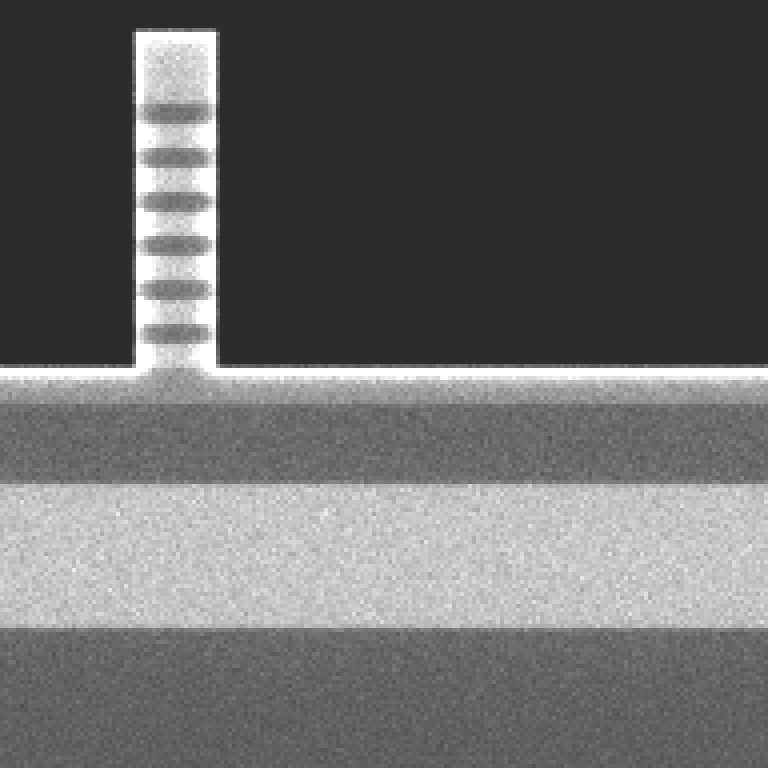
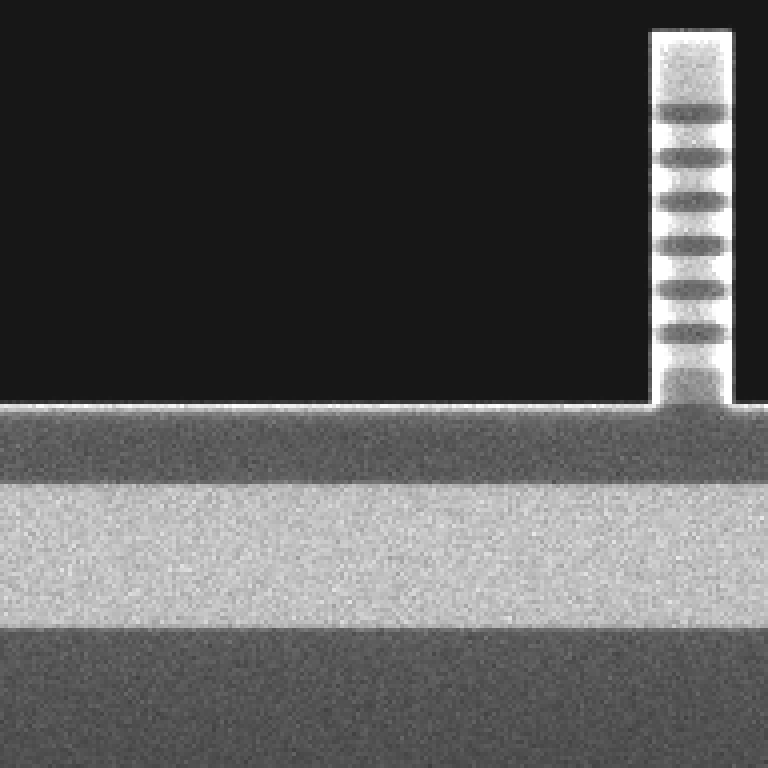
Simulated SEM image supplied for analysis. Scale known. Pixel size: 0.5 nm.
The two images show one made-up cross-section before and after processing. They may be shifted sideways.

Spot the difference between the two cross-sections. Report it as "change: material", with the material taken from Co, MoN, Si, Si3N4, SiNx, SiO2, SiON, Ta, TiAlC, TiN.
removed: SiNx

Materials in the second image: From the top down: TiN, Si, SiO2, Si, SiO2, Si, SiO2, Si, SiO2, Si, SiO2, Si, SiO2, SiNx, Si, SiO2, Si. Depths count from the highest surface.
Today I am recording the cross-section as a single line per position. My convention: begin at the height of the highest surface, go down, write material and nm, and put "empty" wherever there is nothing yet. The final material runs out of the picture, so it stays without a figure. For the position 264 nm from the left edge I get empty 186, Si 40, SiO2 72, Si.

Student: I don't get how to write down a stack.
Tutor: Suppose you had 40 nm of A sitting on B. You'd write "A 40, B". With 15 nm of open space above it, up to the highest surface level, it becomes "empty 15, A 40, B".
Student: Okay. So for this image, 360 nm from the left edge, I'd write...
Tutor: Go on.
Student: TiN 36, Si 10, SiO2 12, Si 10, SiO2 12, Si 10, SiO2 12, Si 10, SiO2 12, Si 10, SiO2 12, Si 10, SiO2 12, SiNx 18, Si 40, SiO2 72, Si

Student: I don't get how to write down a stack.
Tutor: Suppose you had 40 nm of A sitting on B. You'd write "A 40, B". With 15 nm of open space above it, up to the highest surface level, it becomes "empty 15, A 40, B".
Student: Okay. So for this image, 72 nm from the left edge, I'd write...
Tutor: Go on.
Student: empty 186, Si 40, SiO2 72, Si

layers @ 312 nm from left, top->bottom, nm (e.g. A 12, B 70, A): empty 186, Si 40, SiO2 72, Si